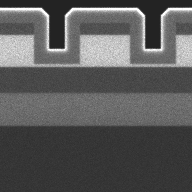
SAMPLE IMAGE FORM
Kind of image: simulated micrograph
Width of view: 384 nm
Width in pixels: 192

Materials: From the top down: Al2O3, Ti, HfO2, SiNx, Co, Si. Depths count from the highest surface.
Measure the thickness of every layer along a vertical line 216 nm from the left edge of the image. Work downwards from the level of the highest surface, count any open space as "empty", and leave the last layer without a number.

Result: Al2O3 30, Ti 24, HfO2 64, SiNx 52, Co 66, Si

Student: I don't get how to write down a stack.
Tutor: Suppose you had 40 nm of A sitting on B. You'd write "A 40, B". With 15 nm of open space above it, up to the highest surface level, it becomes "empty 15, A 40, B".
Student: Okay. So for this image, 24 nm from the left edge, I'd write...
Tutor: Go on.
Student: Al2O3 30, Ti 24, HfO2 64, SiNx 52, Co 66, Si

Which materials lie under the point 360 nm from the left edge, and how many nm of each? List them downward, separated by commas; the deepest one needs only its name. Al2O3 30, Ti 24, HfO2 64, SiNx 52, Co 66, Si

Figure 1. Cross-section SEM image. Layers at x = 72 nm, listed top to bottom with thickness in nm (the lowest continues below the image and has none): Al2O3 112, HfO2 6, SiNx 52, Co 66, Si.